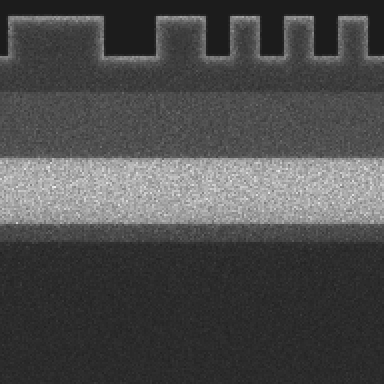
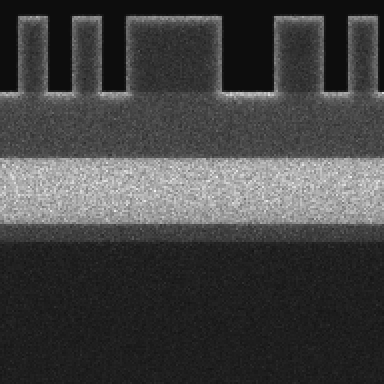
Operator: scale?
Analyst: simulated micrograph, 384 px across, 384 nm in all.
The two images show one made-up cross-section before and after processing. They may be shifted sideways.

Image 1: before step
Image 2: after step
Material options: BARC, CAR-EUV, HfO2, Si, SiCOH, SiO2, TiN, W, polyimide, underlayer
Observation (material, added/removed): underlayer, removed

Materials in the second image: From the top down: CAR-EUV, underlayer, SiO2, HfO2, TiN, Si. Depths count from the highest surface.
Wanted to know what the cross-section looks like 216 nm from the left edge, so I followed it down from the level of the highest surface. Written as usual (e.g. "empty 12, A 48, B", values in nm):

CAR-EUV 40, underlayer 36, SiO2 66, HfO2 66, TiN 18, Si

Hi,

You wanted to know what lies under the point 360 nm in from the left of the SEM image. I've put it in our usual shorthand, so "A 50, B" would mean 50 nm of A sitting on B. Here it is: CAR-EUV 40, underlayer 36, SiO2 66, HfO2 66, TiN 18, Si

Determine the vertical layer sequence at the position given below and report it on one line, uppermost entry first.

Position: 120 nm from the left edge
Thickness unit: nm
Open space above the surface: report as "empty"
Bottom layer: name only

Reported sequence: empty 76, SiO2 66, HfO2 66, TiN 18, Si